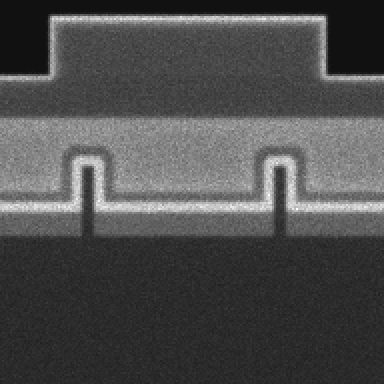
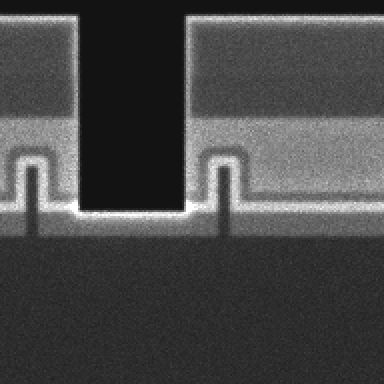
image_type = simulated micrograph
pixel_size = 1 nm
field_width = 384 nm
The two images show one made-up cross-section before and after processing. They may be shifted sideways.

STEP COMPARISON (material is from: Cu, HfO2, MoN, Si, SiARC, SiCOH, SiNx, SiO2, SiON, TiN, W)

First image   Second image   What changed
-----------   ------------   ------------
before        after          HfO2 and SiNx and TiN and W, removed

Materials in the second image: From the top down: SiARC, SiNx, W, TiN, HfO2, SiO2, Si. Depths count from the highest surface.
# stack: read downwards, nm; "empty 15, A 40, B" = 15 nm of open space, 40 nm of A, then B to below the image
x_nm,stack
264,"SiARC 60, SiNx 42, W 74, TiN 10, HfO2 10, SiO2 24, Si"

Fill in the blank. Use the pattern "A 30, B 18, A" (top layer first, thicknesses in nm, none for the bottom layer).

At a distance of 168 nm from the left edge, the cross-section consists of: empty 196, SiO2 24, Si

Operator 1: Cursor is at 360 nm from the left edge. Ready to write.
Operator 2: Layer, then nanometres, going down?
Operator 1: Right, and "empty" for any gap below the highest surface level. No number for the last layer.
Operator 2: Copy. SiARC 60, SiNx 42, W 74, TiN 10, HfO2 10, SiO2 24, Si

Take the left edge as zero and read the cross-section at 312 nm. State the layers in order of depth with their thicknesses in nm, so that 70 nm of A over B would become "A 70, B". SiARC 60, SiNx 42, W 74, TiN 10, HfO2 10, SiO2 24, Si